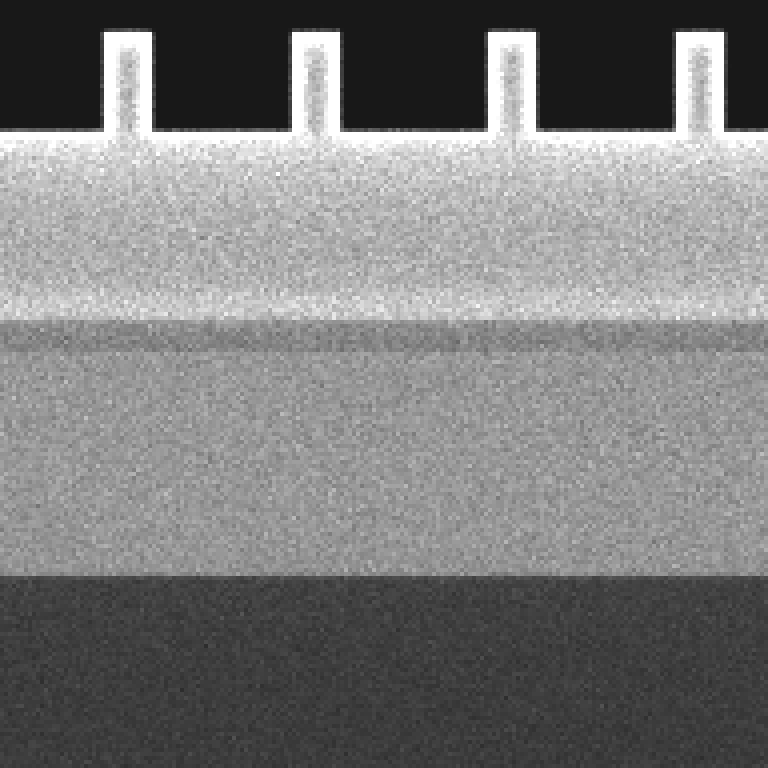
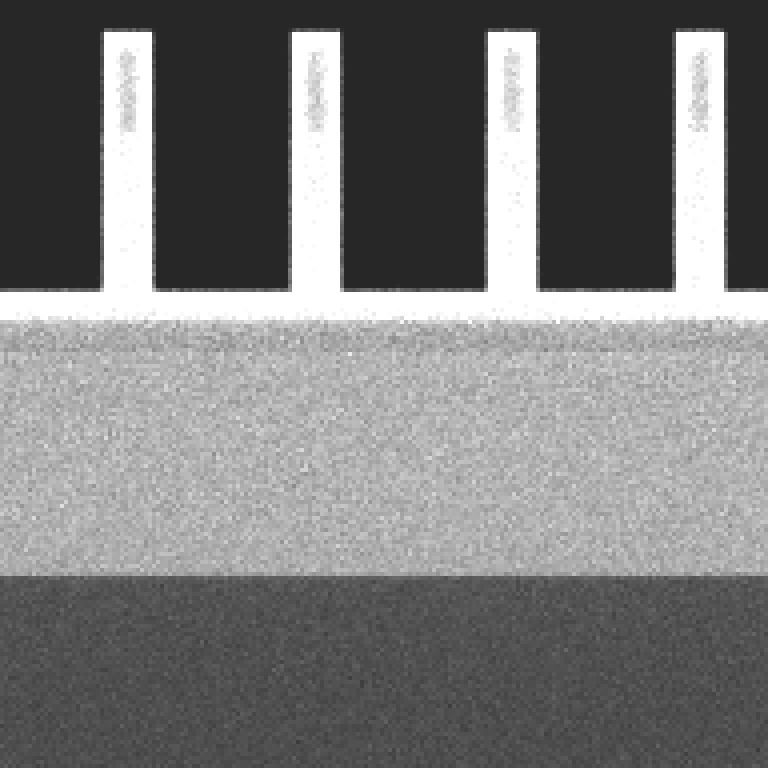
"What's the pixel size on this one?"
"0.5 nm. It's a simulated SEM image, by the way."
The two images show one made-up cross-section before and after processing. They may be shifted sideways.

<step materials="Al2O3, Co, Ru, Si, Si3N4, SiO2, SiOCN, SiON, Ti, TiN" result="removed Co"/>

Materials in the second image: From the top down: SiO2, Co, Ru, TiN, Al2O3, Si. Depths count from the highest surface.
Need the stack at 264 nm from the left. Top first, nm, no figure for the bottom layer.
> SiO2 50, Co 80, Ru 14, TiN 16, Al2O3 112, Si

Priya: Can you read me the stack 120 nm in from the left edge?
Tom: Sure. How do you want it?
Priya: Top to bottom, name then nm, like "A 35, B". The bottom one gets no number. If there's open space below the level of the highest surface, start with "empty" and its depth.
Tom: empty 130, Ru 14, TiN 16, Al2O3 112, Si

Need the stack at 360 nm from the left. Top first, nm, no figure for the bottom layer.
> SiO2 50, Co 80, Ru 14, TiN 16, Al2O3 112, Si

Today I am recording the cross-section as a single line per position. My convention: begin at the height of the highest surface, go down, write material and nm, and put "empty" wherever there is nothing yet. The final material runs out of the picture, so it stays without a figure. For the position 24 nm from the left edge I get empty 130, Ru 14, TiN 16, Al2O3 112, Si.